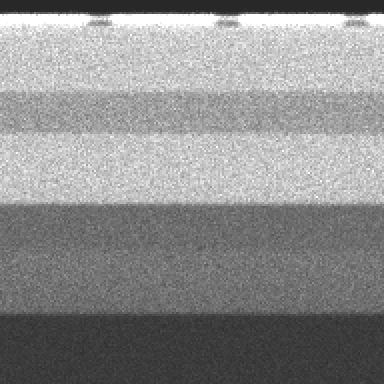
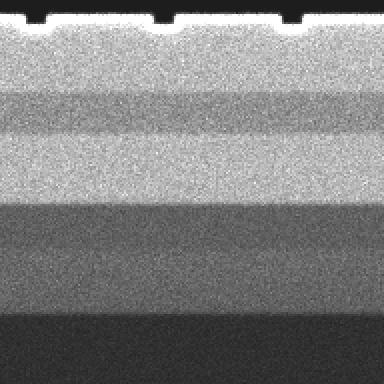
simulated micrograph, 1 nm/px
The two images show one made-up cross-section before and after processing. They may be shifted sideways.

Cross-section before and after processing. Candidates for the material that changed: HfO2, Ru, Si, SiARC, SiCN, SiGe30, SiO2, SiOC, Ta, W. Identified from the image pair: SiARC (removed).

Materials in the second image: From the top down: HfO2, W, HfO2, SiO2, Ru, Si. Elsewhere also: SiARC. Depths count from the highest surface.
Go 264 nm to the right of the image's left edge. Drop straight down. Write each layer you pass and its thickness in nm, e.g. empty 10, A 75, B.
HfO2 76, W 42, HfO2 70, SiO2 46, Ru 64, Si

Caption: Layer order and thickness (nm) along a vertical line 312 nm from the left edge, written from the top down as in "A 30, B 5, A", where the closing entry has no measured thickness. HfO2 76, W 42, HfO2 70, SiO2 46, Ru 64, Si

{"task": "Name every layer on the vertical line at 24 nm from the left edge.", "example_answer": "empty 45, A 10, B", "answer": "empty 10, HfO2 66, W 42, HfO2 70, SiO2 46, Ru 64, Si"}